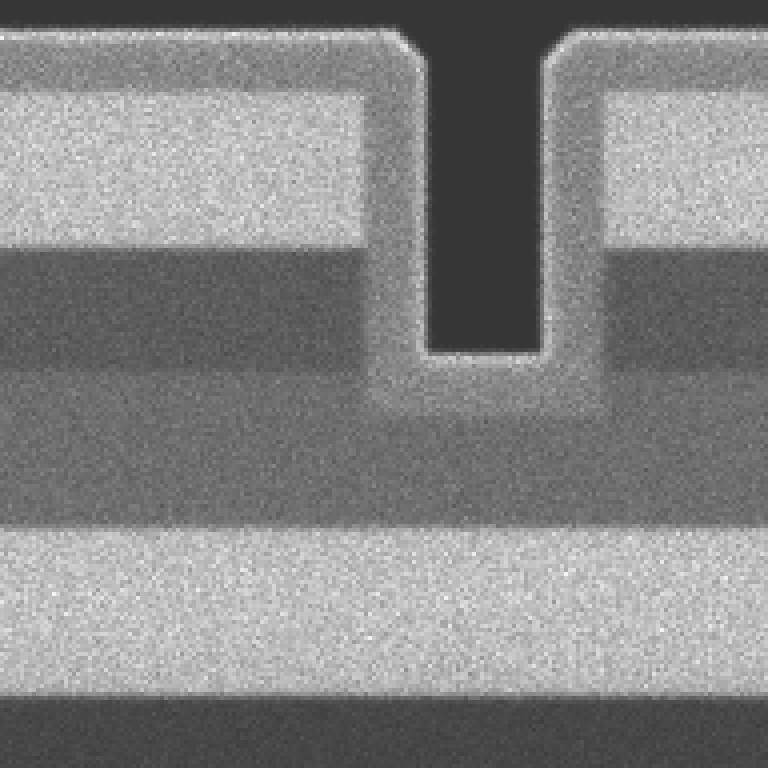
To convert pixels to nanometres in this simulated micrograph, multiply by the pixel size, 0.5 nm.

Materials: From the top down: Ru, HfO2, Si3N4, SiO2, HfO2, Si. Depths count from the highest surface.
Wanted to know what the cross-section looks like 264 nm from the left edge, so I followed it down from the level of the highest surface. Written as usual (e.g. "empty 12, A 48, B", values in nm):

empty 162, Ru 30, SiO2 56, HfO2 84, Si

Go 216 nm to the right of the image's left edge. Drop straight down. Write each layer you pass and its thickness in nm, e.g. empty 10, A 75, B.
empty 162, Ru 30, SiO2 56, HfO2 84, Si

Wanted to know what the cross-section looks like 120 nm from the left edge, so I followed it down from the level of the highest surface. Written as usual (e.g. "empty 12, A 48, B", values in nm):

Ru 30, HfO2 78, Si3N4 62, SiO2 78, HfO2 84, Si